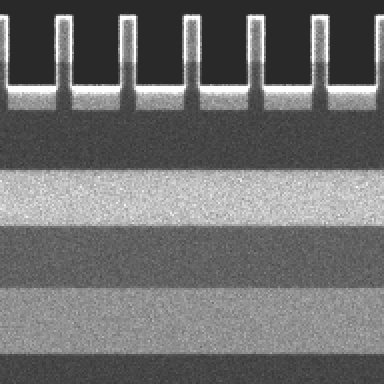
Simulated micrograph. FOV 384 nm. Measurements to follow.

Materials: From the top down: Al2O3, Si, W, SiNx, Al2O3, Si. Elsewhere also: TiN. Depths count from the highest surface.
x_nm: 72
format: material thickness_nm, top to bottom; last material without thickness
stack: empty 70, Al2O3 24, Si 60, W 56, SiNx 62, Al2O3 66, Si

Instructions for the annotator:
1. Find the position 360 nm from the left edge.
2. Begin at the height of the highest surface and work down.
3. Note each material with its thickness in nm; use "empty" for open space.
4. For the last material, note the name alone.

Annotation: empty 70, Al2O3 24, Si 60, W 56, SiNx 62, Al2O3 66, Si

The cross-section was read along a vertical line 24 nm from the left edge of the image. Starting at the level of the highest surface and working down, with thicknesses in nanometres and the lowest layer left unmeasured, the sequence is empty 70, Al2O3 24, Si 60, W 56, SiNx 62, Al2O3 66, Si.